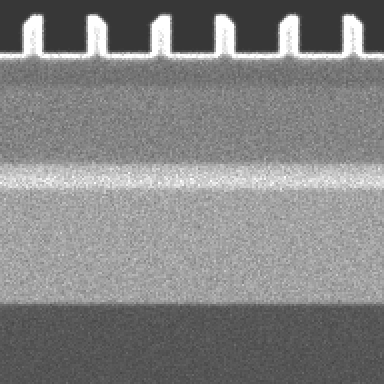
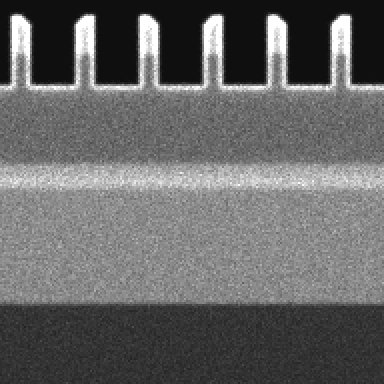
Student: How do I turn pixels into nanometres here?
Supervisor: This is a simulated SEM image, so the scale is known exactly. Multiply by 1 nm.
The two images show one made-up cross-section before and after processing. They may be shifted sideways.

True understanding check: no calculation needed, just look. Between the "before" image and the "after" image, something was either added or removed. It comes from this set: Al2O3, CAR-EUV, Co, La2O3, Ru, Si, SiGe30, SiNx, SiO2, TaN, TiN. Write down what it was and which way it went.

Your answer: SiNx (removed)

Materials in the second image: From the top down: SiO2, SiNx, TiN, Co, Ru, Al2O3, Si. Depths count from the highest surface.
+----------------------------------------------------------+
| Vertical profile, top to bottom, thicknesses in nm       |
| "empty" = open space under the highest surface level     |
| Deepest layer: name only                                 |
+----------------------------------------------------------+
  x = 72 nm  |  empty 70, TiN 78, Co 12, Ru 12, Al2O3 116, Si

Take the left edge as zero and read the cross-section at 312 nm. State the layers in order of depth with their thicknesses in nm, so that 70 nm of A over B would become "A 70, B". empty 70, TiN 78, Co 12, Ru 12, Al2O3 116, Si